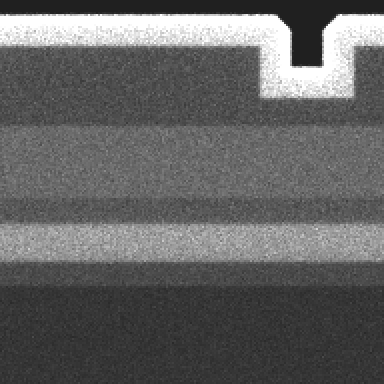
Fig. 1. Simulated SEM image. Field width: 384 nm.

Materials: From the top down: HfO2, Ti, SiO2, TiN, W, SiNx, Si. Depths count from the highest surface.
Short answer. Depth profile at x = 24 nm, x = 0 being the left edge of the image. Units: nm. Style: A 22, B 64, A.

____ HfO2 30, Ti 80, SiO2 72, TiN 26, W 38, SiNx 24, Si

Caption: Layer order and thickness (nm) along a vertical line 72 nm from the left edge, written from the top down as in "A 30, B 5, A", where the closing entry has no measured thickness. HfO2 30, Ti 80, SiO2 72, TiN 26, W 38, SiNx 24, Si